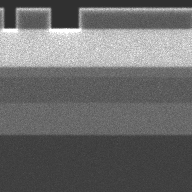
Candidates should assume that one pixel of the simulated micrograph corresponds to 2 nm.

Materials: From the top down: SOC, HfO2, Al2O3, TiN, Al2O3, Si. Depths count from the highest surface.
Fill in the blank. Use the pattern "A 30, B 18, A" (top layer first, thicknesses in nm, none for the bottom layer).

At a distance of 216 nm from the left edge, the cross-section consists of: SOC 42, HfO2 76, Al2O3 20, TiN 52, Al2O3 64, Si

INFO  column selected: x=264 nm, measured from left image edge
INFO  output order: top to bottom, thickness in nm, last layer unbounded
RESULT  SOC 42, HfO2 76, Al2O3 20, TiN 52, Al2O3 64, Si